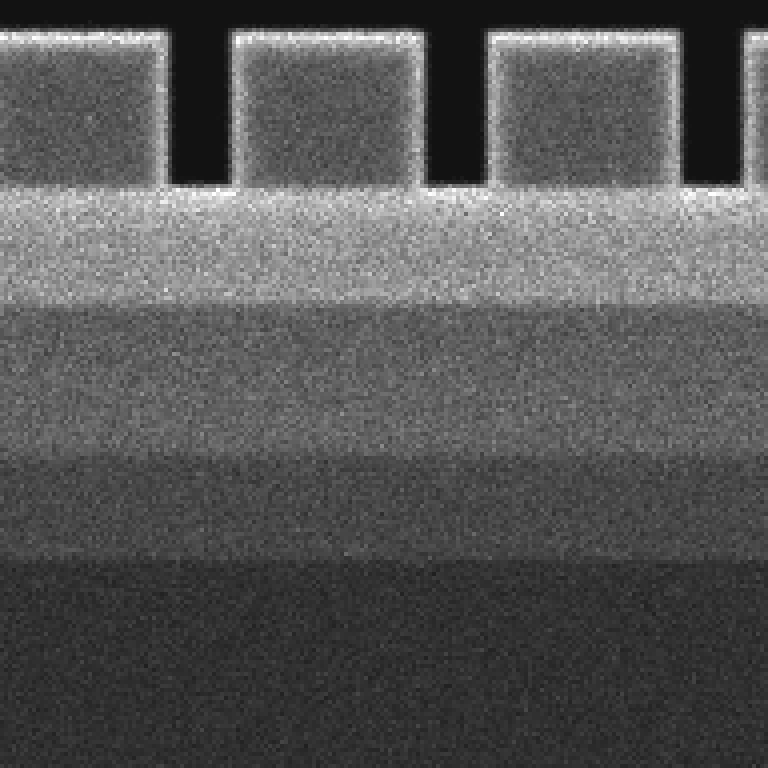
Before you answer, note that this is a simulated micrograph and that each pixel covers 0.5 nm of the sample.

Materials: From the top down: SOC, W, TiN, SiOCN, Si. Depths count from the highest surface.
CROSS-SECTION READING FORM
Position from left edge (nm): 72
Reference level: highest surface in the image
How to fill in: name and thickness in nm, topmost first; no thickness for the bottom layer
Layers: SOC 78, W 58, TiN 76, SiOCN 52, Si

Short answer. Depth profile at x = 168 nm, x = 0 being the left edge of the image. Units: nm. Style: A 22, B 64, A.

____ SOC 78, W 58, TiN 76, SiOCN 52, Si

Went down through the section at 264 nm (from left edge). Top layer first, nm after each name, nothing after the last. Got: SOC 78, W 58, TiN 76, SiOCN 52, Si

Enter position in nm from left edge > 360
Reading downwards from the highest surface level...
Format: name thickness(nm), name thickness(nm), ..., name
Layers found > empty 78, W 58, TiN 76, SiOCN 52, Si